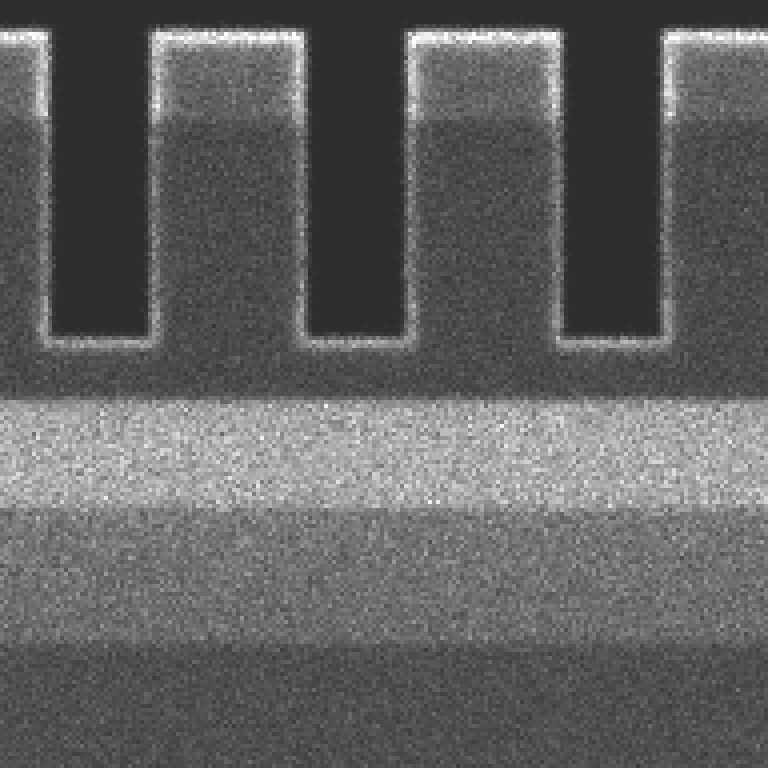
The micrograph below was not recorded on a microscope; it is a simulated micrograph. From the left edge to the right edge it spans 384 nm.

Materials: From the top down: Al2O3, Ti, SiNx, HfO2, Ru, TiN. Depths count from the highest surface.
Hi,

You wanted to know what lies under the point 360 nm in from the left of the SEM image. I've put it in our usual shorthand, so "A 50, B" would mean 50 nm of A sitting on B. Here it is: Al2O3 44, Ti 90, SiNx 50, HfO2 54, Ru 68, TiN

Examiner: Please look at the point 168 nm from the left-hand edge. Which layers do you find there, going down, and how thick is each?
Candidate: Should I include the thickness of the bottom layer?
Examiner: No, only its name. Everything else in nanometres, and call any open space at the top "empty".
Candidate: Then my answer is empty 154, SiNx 30, HfO2 54, Ru 68, TiN